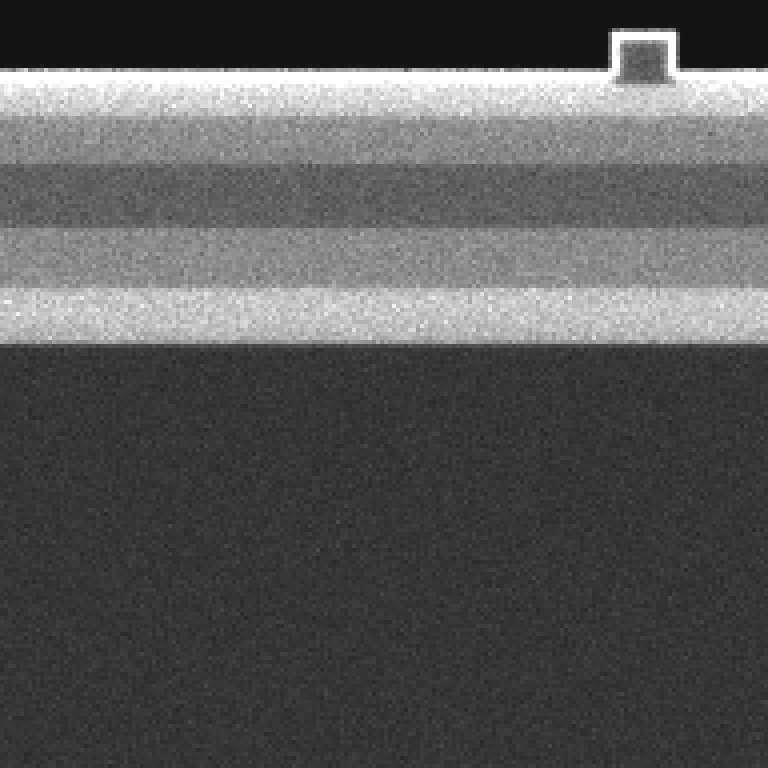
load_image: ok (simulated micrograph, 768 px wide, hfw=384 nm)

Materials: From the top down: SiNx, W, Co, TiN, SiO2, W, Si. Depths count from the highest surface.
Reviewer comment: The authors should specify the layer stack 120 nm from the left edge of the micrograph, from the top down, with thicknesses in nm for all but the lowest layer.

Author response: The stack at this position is empty 20, W 22, Co 24, TiN 32, SiO2 30, W 28, Si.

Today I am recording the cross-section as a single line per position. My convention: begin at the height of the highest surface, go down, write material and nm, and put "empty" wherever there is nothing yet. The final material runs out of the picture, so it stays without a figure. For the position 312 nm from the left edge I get SiNx 26, W 16, Co 24, TiN 32, SiO2 30, W 28, Si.